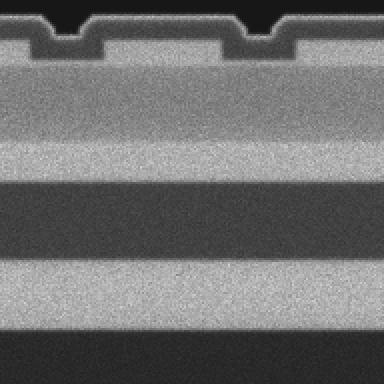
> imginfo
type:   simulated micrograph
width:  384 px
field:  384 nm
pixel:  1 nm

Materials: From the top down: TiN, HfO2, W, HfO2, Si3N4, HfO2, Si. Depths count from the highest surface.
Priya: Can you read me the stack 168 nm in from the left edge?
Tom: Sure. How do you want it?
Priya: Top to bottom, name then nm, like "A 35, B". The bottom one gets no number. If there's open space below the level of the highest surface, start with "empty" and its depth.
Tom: TiN 24, HfO2 26, W 76, HfO2 40, Si3N4 78, HfO2 70, Si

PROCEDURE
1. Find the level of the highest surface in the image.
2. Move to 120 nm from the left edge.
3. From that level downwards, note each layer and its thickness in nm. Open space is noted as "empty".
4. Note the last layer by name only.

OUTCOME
TiN 24, HfO2 26, W 76, HfO2 40, Si3N4 78, HfO2 70, Si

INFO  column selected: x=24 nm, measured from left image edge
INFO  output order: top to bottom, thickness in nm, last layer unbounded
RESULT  TiN 24, HfO2 26, W 76, HfO2 40, Si3N4 78, HfO2 70, Si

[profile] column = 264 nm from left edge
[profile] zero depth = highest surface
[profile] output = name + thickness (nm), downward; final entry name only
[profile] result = empty 20, TiN 24, HfO2 6, W 76, HfO2 40, Si3N4 78, HfO2 70, Si